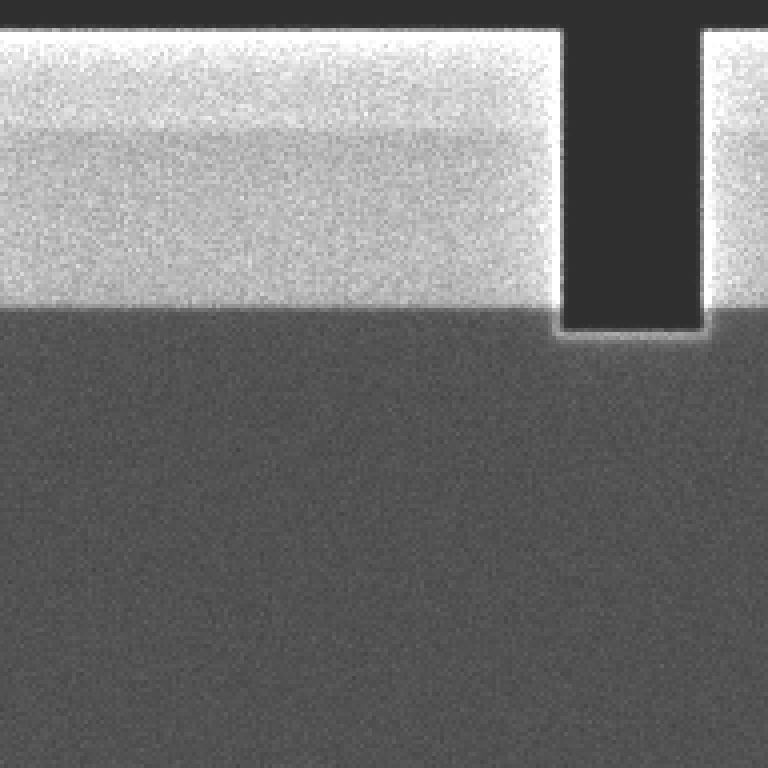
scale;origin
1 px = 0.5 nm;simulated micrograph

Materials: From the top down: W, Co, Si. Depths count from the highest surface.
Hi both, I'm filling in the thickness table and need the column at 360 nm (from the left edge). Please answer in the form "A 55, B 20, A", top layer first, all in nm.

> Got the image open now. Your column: W 48, Co 90, Si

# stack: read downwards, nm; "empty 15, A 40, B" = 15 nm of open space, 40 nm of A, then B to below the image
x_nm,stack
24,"W 48, Co 90, Si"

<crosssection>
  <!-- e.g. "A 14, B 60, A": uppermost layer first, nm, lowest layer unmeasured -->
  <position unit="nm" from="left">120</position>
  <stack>W 48, Co 90, Si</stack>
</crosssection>